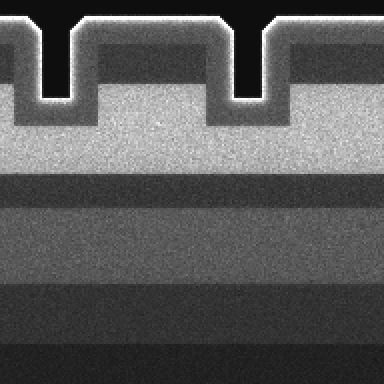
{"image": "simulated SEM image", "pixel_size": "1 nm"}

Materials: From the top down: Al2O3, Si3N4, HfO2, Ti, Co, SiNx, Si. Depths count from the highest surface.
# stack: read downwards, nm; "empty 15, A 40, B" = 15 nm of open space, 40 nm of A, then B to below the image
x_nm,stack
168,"Al2O3 28, Si3N4 40, HfO2 90, Ti 34, Co 76, SiNx 60, Si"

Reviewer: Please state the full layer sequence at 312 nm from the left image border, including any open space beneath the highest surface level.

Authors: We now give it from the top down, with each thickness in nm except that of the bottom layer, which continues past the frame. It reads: Al2O3 28, Si3N4 40, HfO2 90, Ti 34, Co 76, SiNx 60, Si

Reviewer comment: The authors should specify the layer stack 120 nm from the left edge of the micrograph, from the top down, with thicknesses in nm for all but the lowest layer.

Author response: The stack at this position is Al2O3 28, Si3N4 40, HfO2 90, Ti 34, Co 76, SiNx 60, Si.